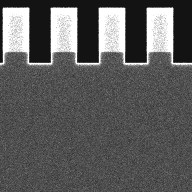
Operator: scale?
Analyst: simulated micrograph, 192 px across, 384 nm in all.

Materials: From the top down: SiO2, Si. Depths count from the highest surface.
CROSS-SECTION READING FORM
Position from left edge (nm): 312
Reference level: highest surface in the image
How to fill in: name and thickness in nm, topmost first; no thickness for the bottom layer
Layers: SiO2 88, Si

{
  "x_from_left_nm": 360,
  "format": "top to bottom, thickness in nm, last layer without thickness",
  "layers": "empty 110, Si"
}